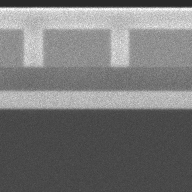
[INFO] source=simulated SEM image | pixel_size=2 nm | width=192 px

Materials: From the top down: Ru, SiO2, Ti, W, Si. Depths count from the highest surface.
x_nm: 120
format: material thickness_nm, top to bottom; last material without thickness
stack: Ru 42, SiO2 76, Ti 48, W 36, Si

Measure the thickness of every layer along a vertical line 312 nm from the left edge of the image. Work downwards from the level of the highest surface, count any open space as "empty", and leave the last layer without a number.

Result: Ru 42, SiO2 76, Ti 48, W 36, Si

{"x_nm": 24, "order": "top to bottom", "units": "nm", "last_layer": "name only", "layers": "Ru 42, SiO2 76, Ti 48, W 36, Si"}